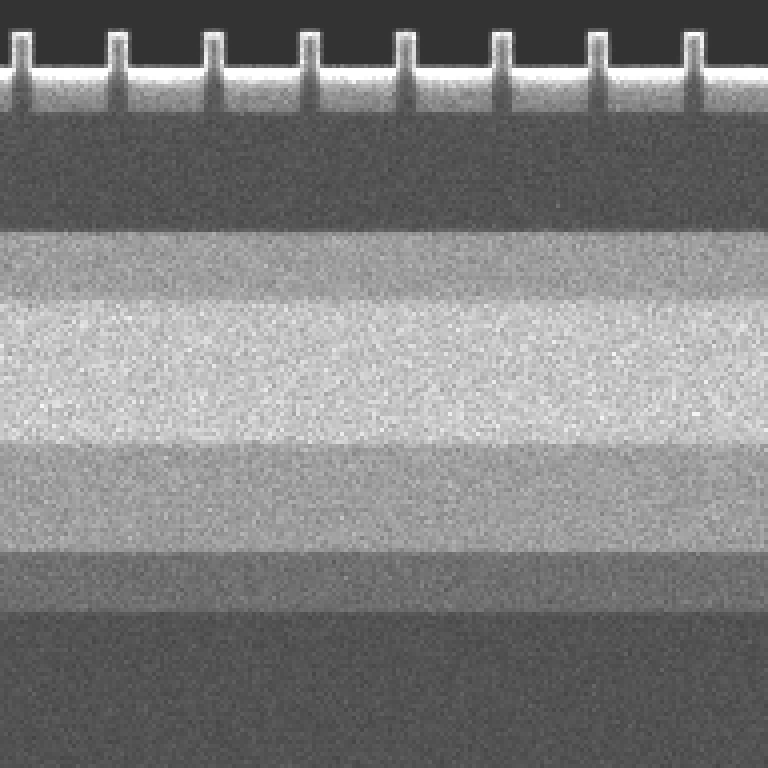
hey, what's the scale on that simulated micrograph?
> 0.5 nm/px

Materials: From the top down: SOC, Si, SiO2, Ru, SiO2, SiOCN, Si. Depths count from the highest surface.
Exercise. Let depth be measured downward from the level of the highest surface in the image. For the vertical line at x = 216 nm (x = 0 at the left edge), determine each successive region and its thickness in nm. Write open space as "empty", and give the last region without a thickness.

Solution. empty 18, SOC 22, Si 60, SiO2 34, Ru 72, SiO2 54, SiOCN 30, Si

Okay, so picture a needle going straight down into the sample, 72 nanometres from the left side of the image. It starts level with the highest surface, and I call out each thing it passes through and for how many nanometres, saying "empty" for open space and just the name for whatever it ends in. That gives empty 18, SOC 22, Si 60, SiO2 34, Ru 72, SiO2 54, SiOCN 30, Si